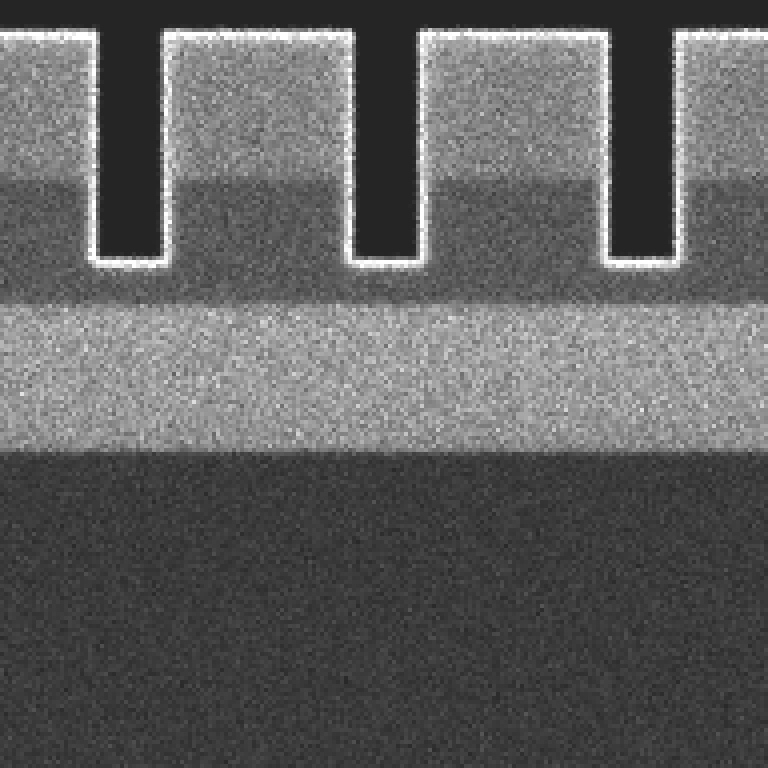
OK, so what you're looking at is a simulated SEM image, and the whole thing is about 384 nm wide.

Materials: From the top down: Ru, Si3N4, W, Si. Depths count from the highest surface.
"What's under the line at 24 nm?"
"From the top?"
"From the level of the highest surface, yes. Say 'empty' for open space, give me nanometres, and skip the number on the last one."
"Ru 74, Si3N4 62, W 74, Si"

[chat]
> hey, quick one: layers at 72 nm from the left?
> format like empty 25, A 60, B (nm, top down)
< empty 114, Si3N4 22, W 74, Si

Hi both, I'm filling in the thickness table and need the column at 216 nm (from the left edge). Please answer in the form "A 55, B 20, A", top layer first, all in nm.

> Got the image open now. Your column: Ru 74, Si3N4 62, W 74, Si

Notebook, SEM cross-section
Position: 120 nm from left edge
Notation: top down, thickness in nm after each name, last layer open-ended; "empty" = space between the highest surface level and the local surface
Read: Ru 74, Si3N4 62, W 74, Si